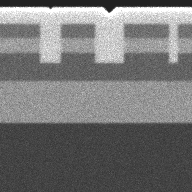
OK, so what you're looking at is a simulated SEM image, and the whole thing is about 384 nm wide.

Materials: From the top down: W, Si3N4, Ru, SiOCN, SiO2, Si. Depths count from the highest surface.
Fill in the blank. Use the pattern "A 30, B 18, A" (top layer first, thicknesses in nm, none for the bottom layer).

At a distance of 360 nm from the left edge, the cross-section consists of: W 32, Si3N4 28, Ru 30, SiOCN 56, SiO2 84, Si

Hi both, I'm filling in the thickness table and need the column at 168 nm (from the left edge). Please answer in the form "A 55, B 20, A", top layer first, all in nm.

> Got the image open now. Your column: W 32, Si3N4 28, Ru 30, SiOCN 56, SiO2 84, Si